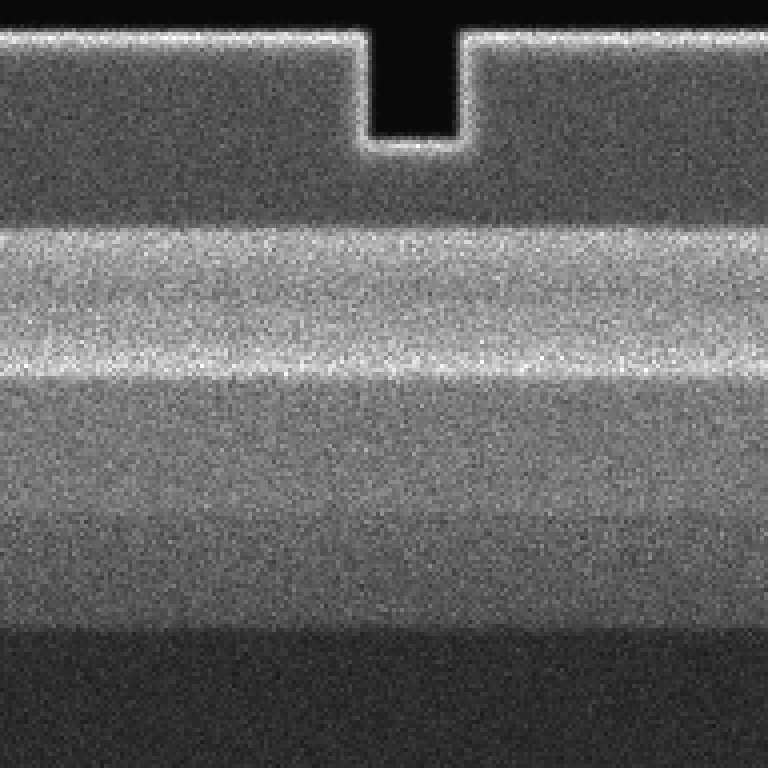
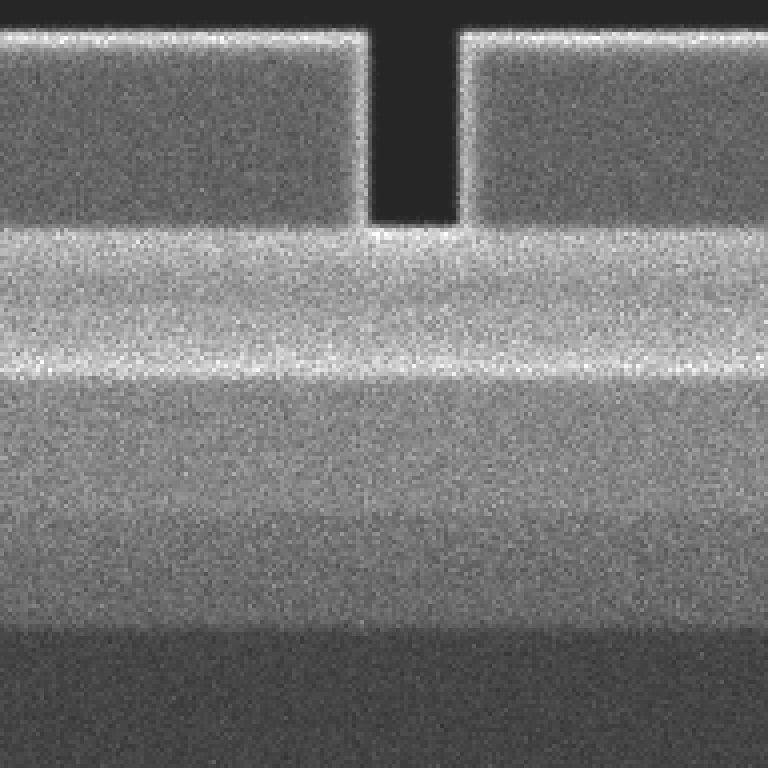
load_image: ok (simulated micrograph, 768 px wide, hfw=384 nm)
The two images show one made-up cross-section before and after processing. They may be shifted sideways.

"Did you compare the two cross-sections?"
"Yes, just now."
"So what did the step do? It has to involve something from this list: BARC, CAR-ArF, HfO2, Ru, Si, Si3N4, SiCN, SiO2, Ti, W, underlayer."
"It removed underlayer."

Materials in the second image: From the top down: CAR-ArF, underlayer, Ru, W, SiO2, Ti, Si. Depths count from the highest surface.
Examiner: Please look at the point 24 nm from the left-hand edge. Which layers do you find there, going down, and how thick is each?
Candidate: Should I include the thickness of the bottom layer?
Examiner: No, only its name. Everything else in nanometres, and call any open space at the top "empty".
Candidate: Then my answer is CAR-ArF 54, underlayer 44, Ru 38, W 36, SiO2 68, Ti 58, Si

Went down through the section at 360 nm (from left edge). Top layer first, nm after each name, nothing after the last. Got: CAR-ArF 54, underlayer 44, Ru 38, W 36, SiO2 68, Ti 58, Si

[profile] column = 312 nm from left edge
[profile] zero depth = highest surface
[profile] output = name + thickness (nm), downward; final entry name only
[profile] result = CAR-ArF 54, underlayer 44, Ru 38, W 36, SiO2 68, Ti 58, Si